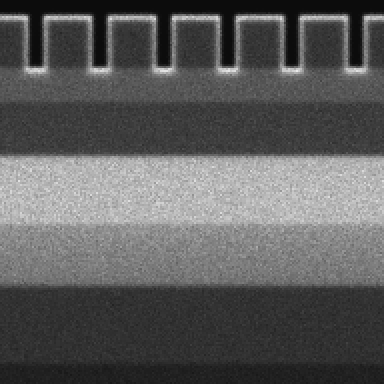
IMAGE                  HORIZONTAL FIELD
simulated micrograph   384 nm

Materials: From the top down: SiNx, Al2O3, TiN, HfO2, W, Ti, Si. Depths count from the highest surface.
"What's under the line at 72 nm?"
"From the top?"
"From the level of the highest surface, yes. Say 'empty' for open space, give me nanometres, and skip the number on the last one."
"SiNx 52, Al2O3 34, TiN 54, HfO2 68, W 62, Ti 78, Si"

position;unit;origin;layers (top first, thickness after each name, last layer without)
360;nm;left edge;empty 52, Al2O3 34, TiN 54, HfO2 68, W 62, Ti 78, Si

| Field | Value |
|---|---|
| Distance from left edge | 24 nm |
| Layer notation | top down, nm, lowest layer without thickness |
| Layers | SiNx 52, Al2O3 34, TiN 54, HfO2 68, W 62, Ti 78, Si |